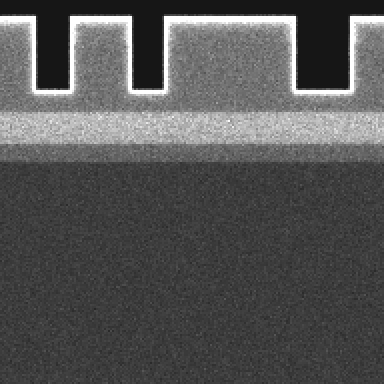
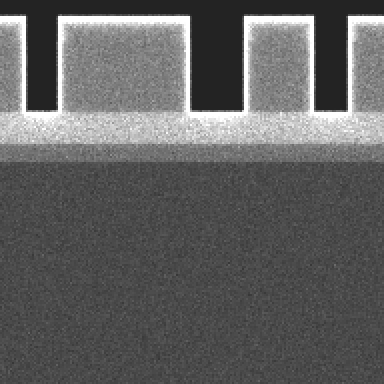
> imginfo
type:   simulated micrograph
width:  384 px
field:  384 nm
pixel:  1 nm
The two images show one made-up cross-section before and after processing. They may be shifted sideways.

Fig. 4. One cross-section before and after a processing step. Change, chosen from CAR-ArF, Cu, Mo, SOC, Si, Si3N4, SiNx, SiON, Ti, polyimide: Si3N4 removed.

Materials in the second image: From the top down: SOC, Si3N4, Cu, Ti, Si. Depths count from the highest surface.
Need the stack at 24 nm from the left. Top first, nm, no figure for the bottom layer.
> SOC 26, Si3N4 70, Cu 32, Ti 18, Si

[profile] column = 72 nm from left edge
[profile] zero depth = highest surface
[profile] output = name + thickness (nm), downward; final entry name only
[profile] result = SOC 26, Si3N4 70, Cu 32, Ti 18, Si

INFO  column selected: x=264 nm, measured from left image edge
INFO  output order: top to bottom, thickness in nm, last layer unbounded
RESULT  SOC 26, Si3N4 70, Cu 32, Ti 18, Si